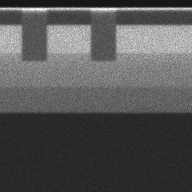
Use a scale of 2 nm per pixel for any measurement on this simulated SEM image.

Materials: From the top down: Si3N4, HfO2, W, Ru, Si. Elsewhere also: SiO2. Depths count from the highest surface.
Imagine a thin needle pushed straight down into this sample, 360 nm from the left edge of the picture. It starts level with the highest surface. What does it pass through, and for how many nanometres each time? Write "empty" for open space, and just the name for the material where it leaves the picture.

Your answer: Si3N4 34, HfO2 56, W 68, Ru 52, Si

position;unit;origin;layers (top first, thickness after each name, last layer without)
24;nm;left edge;Si3N4 34, HfO2 56, W 68, Ru 52, Si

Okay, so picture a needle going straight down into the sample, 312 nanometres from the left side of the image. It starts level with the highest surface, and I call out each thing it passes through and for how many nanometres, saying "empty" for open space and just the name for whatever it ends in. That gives Si3N4 34, HfO2 56, W 68, Ru 52, Si